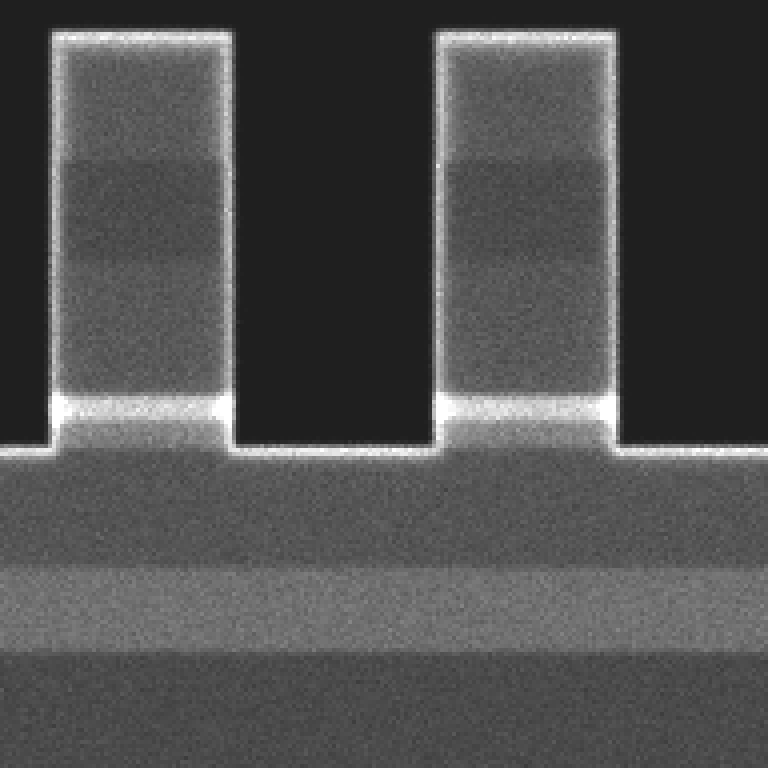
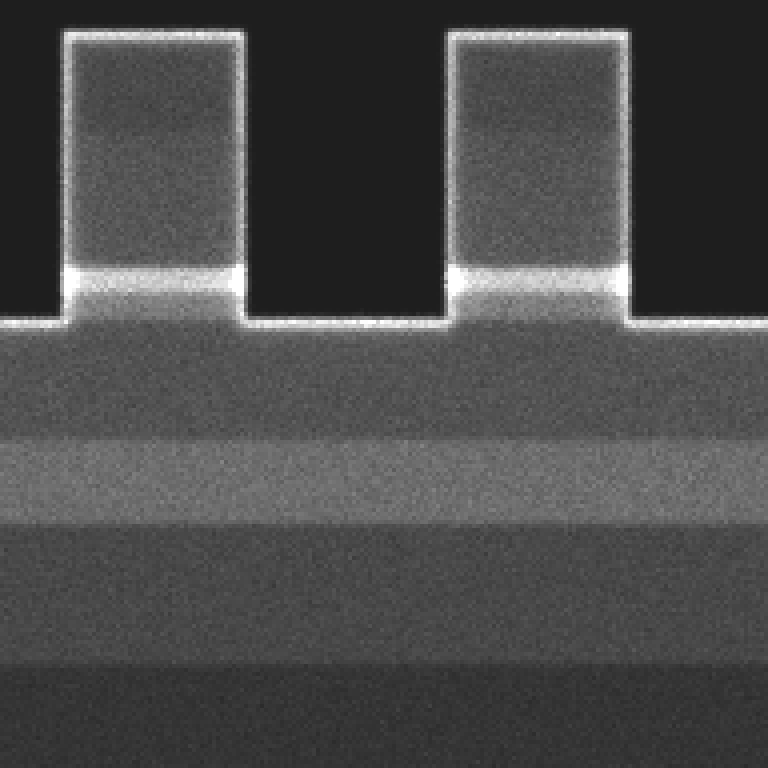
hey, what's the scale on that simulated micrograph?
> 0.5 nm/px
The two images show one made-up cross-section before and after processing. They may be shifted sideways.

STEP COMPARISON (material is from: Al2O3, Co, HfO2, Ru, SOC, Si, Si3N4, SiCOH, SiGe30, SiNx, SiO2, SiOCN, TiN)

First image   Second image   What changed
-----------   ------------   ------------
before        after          SOC, removed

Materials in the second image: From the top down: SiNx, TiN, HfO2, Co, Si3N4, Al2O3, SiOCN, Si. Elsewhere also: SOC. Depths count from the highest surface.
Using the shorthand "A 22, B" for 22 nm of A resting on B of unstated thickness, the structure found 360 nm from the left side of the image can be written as empty 144, Si3N4 60, Al2O3 42, SiOCN 70, Si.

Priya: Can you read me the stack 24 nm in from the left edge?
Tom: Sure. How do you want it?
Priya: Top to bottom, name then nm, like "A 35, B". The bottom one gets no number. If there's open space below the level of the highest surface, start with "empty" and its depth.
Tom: empty 144, Si3N4 60, Al2O3 42, SiOCN 70, Si